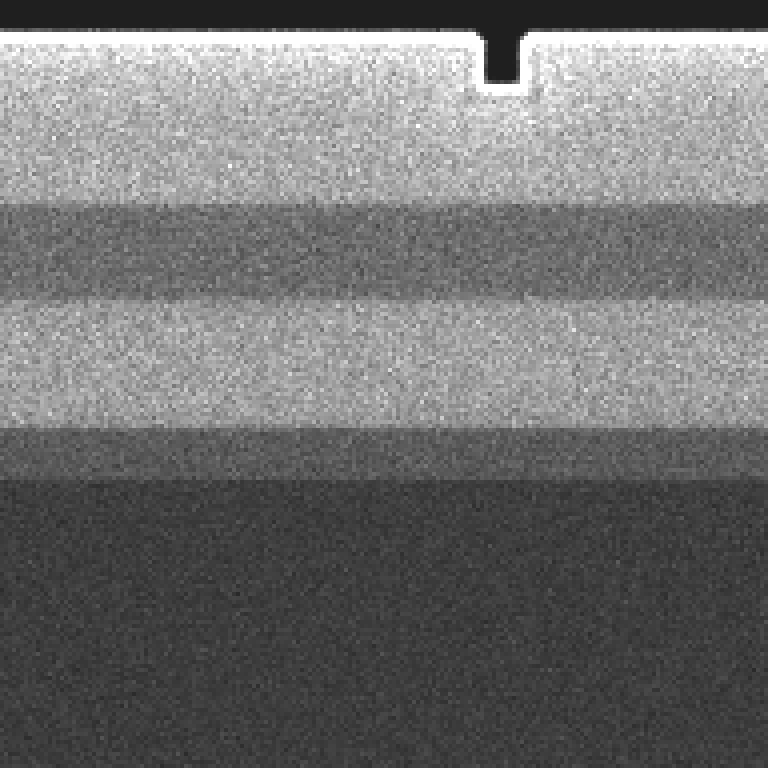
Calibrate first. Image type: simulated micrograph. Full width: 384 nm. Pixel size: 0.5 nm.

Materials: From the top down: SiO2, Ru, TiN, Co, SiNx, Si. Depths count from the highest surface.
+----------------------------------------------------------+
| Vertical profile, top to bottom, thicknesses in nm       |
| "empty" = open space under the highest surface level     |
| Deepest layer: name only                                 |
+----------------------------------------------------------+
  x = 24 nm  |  SiO2 10, Ru 76, TiN 48, Co 64, SiNx 26, Si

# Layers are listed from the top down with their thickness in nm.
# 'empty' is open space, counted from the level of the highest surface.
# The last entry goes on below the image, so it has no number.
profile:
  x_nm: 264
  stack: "SiO2 36, Ru 50, TiN 48, Co 64, SiNx 26, Si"